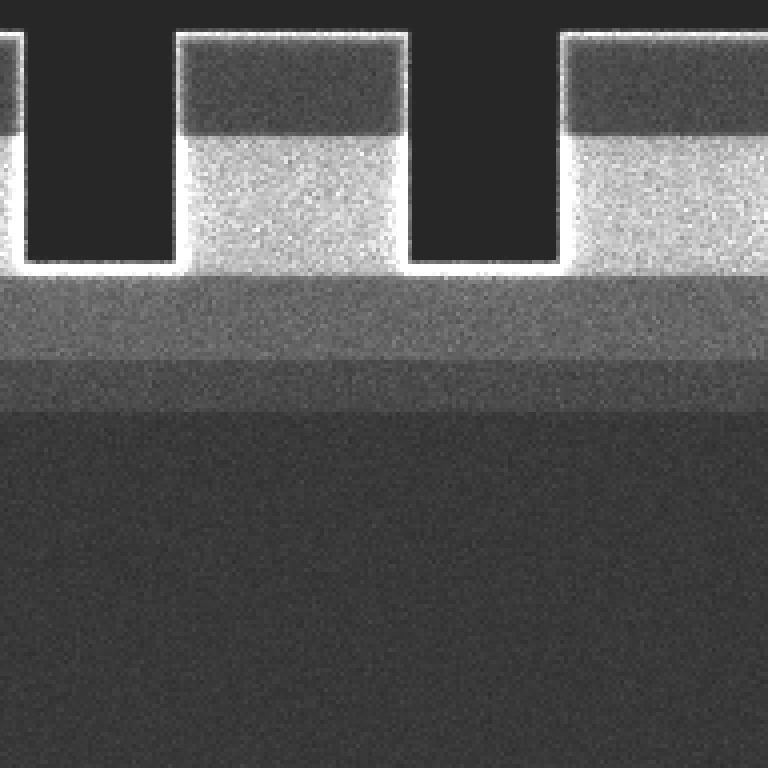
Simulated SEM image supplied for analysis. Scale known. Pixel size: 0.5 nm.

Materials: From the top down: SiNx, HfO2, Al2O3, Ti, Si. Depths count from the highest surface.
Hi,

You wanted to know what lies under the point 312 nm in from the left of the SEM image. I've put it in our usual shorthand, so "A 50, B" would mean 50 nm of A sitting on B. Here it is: SiNx 52, HfO2 70, Al2O3 42, Ti 26, Si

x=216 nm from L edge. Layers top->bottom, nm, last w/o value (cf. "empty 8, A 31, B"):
empty 116, HfO2 6, Al2O3 42, Ti 26, Si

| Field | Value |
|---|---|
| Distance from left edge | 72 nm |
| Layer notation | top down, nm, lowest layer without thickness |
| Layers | empty 116, HfO2 6, Al2O3 42, Ti 26, Si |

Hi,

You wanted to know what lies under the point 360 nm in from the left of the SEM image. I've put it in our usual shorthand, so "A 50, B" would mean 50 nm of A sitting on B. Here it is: SiNx 52, HfO2 70, Al2O3 42, Ti 26, Si